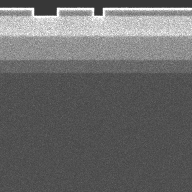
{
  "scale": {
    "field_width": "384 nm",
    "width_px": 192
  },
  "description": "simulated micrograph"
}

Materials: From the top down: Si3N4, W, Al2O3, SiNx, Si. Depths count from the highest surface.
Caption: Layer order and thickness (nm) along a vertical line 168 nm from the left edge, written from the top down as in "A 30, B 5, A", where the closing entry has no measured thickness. Si3N4 16, W 40, Al2O3 48, SiNx 26, Si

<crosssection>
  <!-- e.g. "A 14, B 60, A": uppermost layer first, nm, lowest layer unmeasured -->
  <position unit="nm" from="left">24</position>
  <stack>Si3N4 16, W 40, Al2O3 48, SiNx 26, Si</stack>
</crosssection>